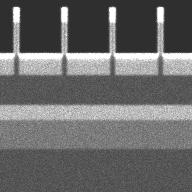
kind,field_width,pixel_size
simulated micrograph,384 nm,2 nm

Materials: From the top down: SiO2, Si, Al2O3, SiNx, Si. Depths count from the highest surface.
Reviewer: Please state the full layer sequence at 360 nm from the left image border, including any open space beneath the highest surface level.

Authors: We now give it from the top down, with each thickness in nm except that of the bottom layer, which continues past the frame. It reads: empty 92, SiO2 42, Si 60, Al2O3 30, SiNx 58, Si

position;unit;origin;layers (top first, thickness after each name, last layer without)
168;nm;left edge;empty 92, SiO2 42, Si 60, Al2O3 30, SiNx 58, Si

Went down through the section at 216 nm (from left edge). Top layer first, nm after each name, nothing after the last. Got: empty 92, SiO2 42, Si 60, Al2O3 30, SiNx 58, Si